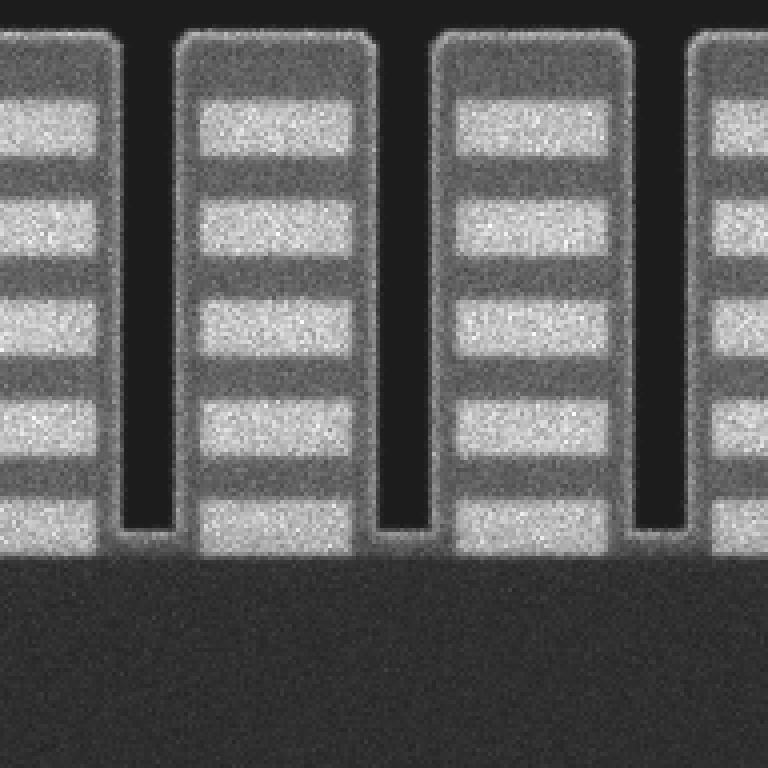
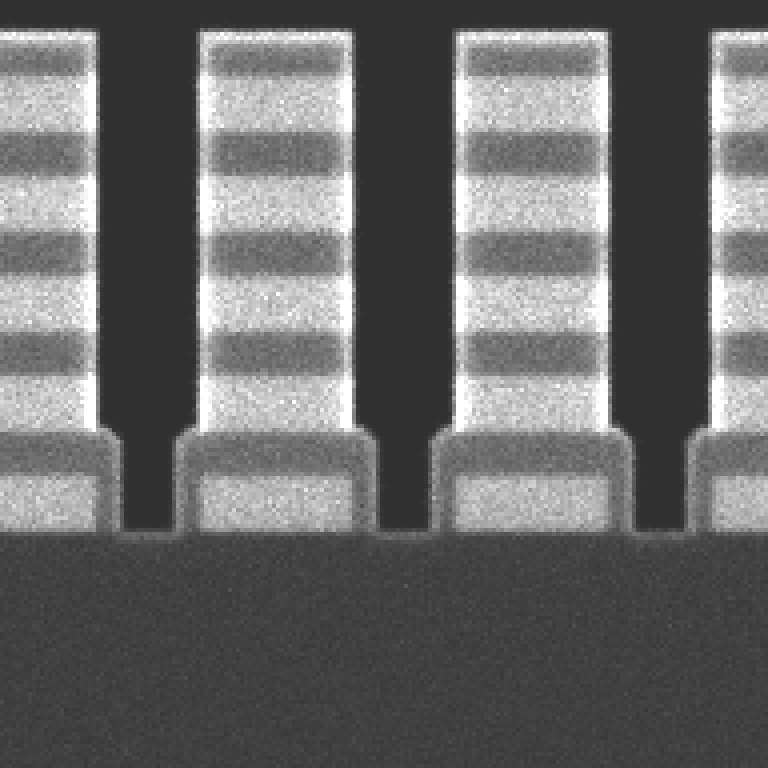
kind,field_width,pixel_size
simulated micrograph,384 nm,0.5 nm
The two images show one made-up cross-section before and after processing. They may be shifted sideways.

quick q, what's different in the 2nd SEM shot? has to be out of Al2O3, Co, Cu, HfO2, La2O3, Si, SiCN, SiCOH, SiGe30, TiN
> TiN removed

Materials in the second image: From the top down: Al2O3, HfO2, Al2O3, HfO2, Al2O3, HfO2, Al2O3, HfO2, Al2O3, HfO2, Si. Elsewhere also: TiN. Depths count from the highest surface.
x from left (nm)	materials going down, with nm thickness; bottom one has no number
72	empty 250, Si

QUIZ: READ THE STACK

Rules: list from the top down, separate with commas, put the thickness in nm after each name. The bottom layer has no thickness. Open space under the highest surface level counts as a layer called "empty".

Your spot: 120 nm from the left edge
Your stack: Al2O3 22, HfO2 28, Al2O3 22, HfO2 28, Al2O3 22, HfO2 28, Al2O3 22, HfO2 28, Al2O3 22, HfO2 28, Si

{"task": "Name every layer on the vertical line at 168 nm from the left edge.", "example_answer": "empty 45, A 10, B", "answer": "Al2O3 22, HfO2 28, Al2O3 22, HfO2 28, Al2O3 22, HfO2 28, Al2O3 22, HfO2 28, Al2O3 22, HfO2 28, Si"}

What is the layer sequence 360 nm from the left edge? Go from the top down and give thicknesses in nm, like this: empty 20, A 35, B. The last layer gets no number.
Al2O3 22, HfO2 28, Al2O3 22, HfO2 28, Al2O3 22, HfO2 28, Al2O3 22, HfO2 28, Al2O3 22, HfO2 28, Si